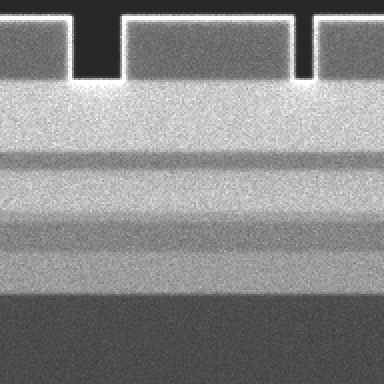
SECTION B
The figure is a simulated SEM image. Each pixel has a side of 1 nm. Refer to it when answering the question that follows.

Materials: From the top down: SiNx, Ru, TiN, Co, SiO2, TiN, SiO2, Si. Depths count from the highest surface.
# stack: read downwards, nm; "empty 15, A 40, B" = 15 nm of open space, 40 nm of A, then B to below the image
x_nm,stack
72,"empty 64, Ru 72, TiN 18, Co 42, SiO2 10, TiN 30, SiO2 42, Si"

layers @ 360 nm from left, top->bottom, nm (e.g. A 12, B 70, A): SiNx 64, Ru 72, TiN 18, Co 42, SiO2 10, TiN 30, SiO2 42, Si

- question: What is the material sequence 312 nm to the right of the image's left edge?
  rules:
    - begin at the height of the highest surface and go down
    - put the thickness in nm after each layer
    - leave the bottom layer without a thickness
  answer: empty 64, Ru 72, TiN 18, Co 42, SiO2 10, TiN 30, SiO2 42, Si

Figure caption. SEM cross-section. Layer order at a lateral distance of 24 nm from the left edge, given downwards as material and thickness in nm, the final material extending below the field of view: SiNx 64, Ru 72, TiN 18, Co 42, SiO2 10, TiN 30, SiO2 42, Si